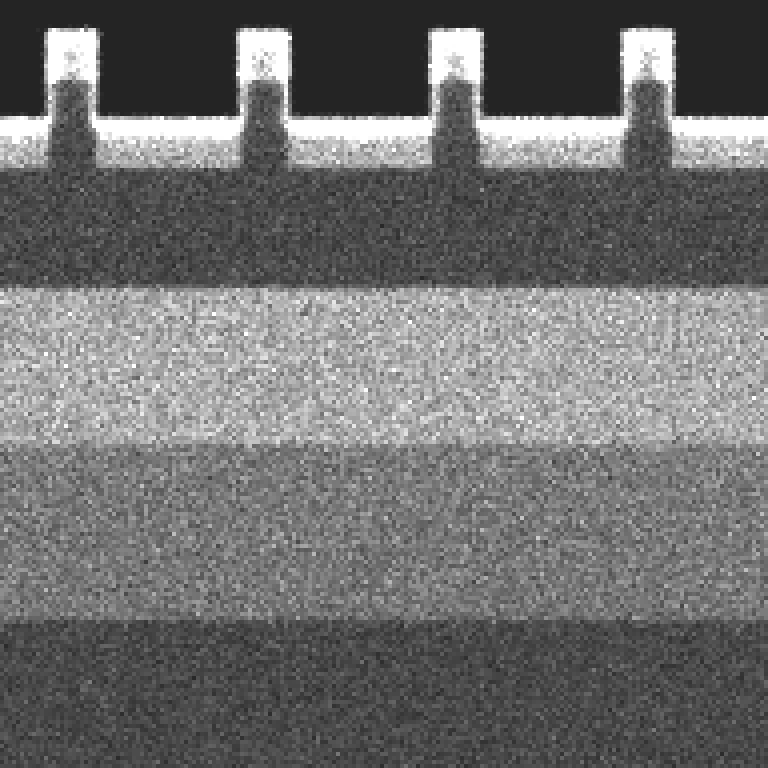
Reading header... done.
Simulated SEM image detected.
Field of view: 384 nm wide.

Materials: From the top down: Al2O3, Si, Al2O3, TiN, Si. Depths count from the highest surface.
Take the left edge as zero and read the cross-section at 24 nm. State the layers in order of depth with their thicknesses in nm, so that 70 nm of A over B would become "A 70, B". Al2O3 24, Si 104, Al2O3 78, TiN 88, Si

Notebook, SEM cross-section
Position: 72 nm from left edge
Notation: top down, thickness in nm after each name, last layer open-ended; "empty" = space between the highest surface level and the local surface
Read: empty 44, Al2O3 24, Si 60, Al2O3 78, TiN 88, Si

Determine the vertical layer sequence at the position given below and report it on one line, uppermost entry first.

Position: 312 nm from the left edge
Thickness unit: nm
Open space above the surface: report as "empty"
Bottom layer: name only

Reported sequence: Al2O3 24, Si 104, Al2O3 78, TiN 88, Si